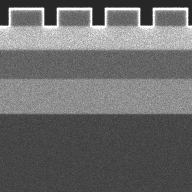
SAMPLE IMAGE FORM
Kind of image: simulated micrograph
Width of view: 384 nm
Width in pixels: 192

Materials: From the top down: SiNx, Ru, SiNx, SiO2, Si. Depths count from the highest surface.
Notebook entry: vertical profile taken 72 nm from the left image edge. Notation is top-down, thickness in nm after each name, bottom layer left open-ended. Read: SiNx 36, Ru 48, SiNx 58, SiO2 70, Si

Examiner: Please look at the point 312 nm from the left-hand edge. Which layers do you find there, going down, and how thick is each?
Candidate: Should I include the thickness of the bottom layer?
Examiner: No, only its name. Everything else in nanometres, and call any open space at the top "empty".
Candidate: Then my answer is SiNx 36, Ru 48, SiNx 58, SiO2 70, Si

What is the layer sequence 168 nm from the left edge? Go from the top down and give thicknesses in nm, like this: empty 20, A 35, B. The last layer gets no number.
SiNx 36, Ru 48, SiNx 58, SiO2 70, Si